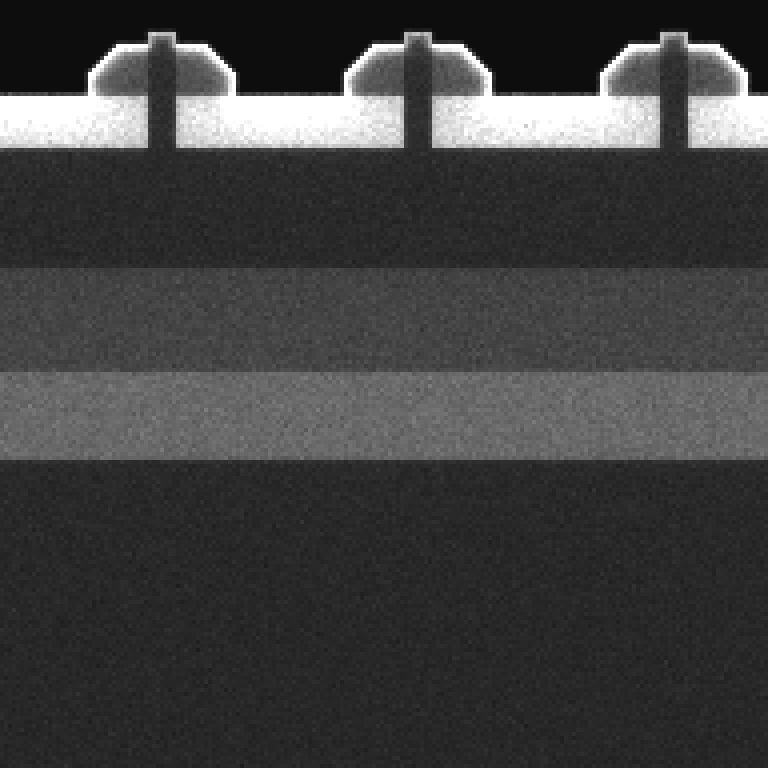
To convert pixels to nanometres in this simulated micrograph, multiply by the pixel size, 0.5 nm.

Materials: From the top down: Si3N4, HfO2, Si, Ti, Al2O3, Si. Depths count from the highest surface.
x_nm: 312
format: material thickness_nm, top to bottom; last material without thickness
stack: empty 8, Si3N4 24, HfO2 26, Si 60, Ti 52, Al2O3 44, Si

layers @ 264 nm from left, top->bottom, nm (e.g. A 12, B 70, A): empty 32, HfO2 26, Si 60, Ti 52, Al2O3 44, Si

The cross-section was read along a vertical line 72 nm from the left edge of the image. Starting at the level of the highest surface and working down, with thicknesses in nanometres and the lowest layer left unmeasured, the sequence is empty 6, Si3N4 26, HfO2 26, Si 60, Ti 52, Al2O3 44, Si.